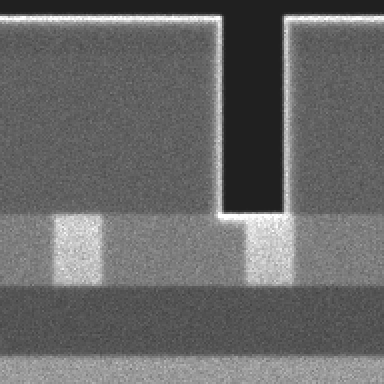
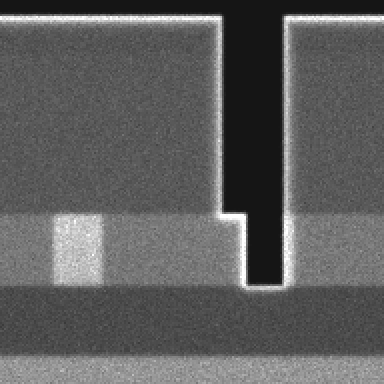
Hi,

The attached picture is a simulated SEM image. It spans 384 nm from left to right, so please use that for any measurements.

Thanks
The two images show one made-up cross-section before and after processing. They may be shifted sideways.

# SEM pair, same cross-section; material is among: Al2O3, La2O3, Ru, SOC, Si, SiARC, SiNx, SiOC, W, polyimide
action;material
removed;W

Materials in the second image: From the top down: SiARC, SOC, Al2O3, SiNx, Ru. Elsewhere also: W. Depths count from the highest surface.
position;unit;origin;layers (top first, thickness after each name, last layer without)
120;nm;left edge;SiARC 38, SOC 160, Al2O3 72, SiNx 70, Ru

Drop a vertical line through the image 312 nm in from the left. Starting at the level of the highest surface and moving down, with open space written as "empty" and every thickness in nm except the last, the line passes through SiARC 38, SOC 160, Al2O3 72, SiNx 70, Ru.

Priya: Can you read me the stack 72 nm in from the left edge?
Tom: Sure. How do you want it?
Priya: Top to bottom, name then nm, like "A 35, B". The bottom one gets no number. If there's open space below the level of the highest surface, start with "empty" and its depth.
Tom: SiARC 38, SOC 160, W 72, SiNx 70, Ru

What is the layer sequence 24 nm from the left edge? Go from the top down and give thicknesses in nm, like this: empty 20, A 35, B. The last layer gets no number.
SiARC 38, SOC 160, Al2O3 72, SiNx 70, Ru